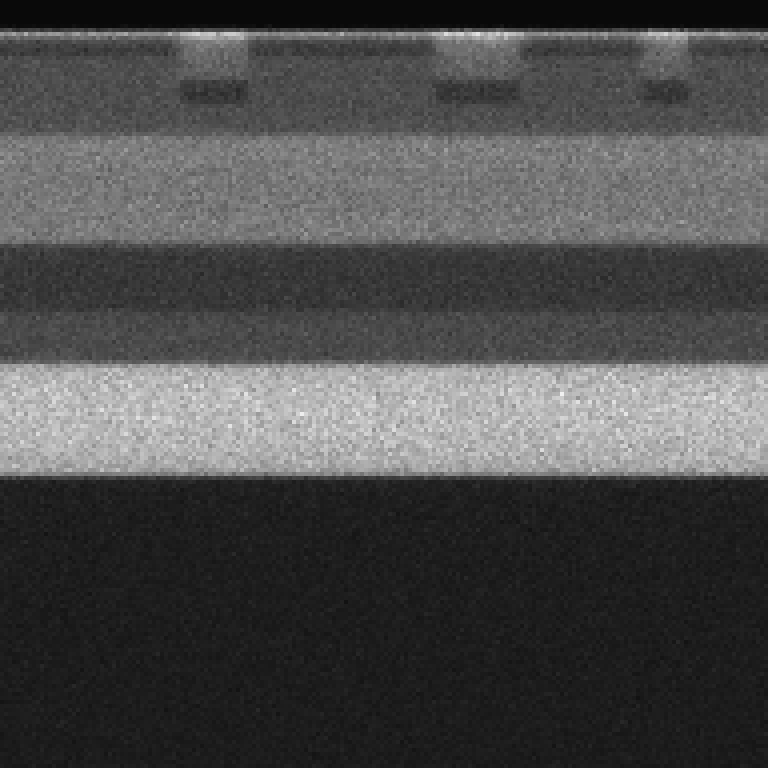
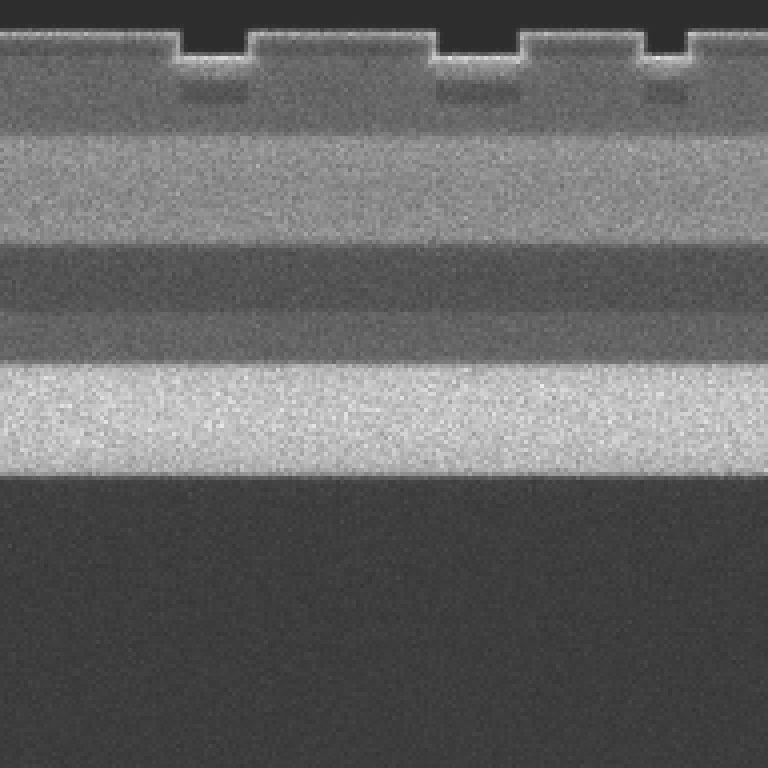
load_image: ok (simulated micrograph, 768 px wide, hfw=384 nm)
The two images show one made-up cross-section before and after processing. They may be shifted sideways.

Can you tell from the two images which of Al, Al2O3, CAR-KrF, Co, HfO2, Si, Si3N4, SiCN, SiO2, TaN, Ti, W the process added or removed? Yes, it removed Co.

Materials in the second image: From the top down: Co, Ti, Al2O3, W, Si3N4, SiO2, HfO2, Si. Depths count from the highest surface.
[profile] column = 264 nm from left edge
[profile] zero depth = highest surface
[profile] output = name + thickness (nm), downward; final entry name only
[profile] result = Ti 12, Al2O3 40, W 54, Si3N4 34, SiO2 26, HfO2 56, Si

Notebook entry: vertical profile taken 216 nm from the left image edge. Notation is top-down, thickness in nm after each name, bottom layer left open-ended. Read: Ti 12, Al2O3 40, W 54, Si3N4 34, SiO2 26, HfO2 56, Si